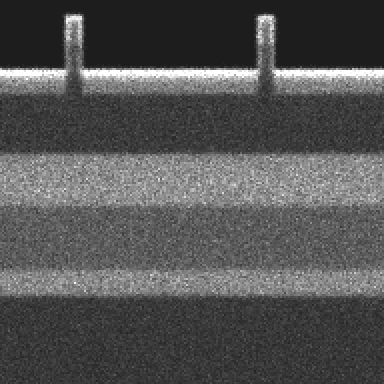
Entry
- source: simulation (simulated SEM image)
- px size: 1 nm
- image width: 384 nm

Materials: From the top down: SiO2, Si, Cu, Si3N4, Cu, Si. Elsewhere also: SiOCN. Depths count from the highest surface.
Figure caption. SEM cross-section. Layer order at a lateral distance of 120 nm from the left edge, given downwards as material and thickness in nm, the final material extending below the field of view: empty 54, SiO2 24, Si 60, Cu 52, Si3N4 64, Cu 26, Si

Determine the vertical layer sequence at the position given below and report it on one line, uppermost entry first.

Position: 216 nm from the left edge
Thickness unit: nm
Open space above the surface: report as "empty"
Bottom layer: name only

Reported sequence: empty 54, SiO2 24, Si 60, Cu 52, Si3N4 64, Cu 26, Si